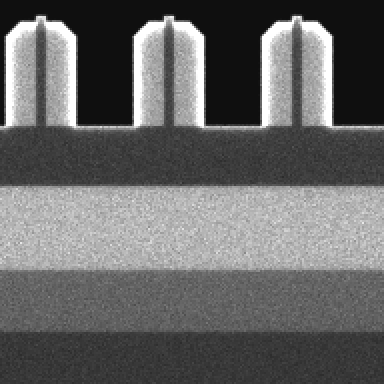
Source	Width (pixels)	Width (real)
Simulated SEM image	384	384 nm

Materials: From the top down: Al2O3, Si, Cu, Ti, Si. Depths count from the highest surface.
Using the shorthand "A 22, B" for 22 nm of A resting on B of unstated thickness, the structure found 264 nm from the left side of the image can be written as empty 18, Al2O3 92, Si 60, Cu 84, Ti 62, Si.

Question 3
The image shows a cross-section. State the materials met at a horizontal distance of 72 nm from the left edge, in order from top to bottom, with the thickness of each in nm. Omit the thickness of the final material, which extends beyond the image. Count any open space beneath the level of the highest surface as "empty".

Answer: empty 18, Al2O3 92, Si 60, Cu 84, Ti 62, Si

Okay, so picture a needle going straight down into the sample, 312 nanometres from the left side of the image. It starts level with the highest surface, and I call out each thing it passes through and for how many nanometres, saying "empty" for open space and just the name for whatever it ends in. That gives empty 6, Al2O3 104, Si 60, Cu 84, Ti 62, Si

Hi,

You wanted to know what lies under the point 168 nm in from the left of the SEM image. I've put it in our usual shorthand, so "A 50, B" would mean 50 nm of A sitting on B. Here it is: Si 170, Cu 84, Ti 62, Si